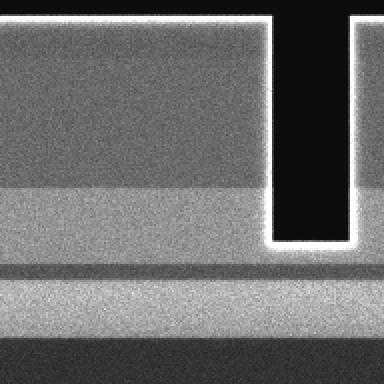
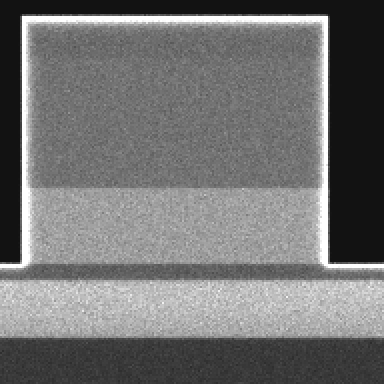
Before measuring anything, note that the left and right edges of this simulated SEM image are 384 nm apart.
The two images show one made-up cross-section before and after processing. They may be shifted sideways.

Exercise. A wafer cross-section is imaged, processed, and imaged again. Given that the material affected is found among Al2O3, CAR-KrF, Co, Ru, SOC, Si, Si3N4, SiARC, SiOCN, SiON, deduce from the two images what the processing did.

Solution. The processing removed Al2O3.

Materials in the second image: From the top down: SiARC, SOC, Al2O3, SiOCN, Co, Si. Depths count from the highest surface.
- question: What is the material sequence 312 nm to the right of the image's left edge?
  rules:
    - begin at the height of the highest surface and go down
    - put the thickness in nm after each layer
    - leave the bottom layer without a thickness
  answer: SiARC 42, SOC 130, Al2O3 76, SiOCN 16, Co 58, Si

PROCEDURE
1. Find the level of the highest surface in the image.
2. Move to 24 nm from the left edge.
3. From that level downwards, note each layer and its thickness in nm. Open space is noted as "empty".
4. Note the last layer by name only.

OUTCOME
SiARC 42, SOC 130, Al2O3 76, SiOCN 16, Co 58, Si